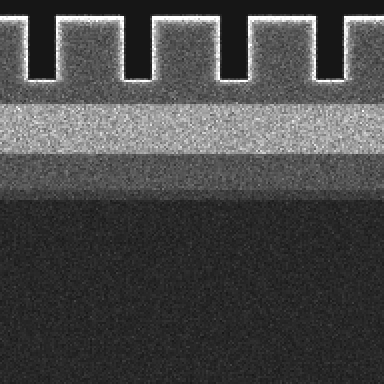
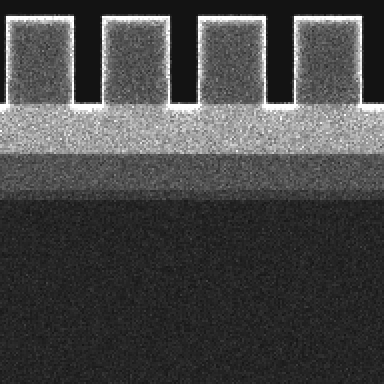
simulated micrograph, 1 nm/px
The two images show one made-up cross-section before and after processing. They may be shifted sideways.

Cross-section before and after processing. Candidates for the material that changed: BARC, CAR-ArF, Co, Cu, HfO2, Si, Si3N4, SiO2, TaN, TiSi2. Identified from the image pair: Co (removed).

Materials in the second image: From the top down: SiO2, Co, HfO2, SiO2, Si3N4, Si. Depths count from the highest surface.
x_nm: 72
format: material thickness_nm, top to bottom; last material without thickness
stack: SiO2 64, Co 24, HfO2 50, SiO2 36, Si3N4 10, Si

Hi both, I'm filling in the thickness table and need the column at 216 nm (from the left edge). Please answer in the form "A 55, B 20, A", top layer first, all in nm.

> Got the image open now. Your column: SiO2 64, Co 24, HfO2 50, SiO2 36, Si3N4 10, Si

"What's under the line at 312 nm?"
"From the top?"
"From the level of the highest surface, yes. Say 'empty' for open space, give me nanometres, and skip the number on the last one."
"SiO2 64, Co 24, HfO2 50, SiO2 36, Si3N4 10, Si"